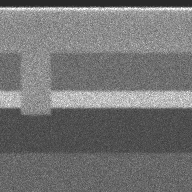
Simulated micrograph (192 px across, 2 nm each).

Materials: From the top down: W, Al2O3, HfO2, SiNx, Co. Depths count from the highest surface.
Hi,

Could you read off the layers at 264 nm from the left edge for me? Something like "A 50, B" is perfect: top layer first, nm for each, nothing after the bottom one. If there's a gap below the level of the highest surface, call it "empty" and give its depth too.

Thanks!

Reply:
W 90, Al2O3 76, HfO2 34, SiNx 90, Co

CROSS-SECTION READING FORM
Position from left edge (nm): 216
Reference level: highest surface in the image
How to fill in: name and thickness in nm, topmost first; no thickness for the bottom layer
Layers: W 90, Al2O3 76, HfO2 34, SiNx 90, Co